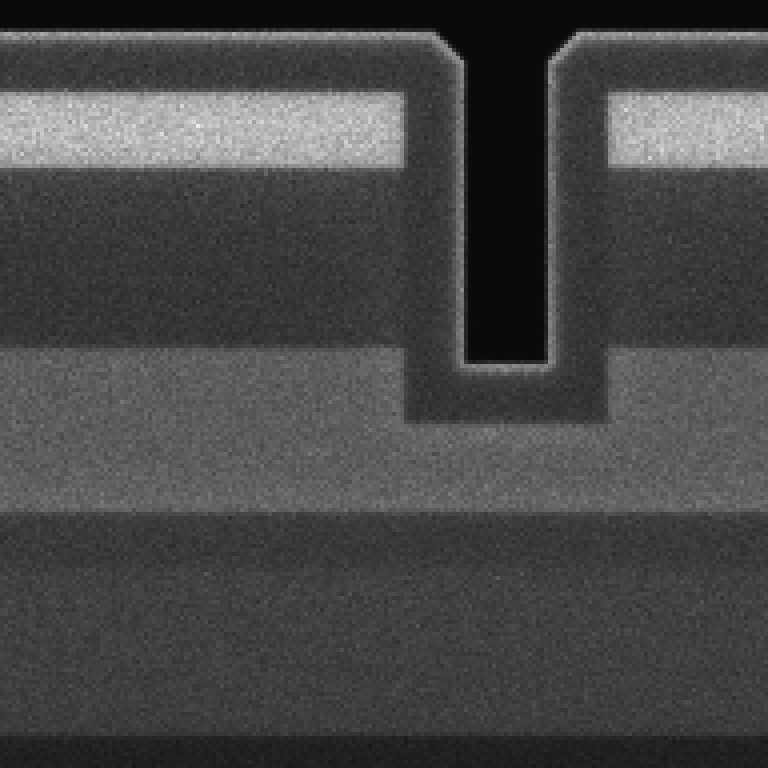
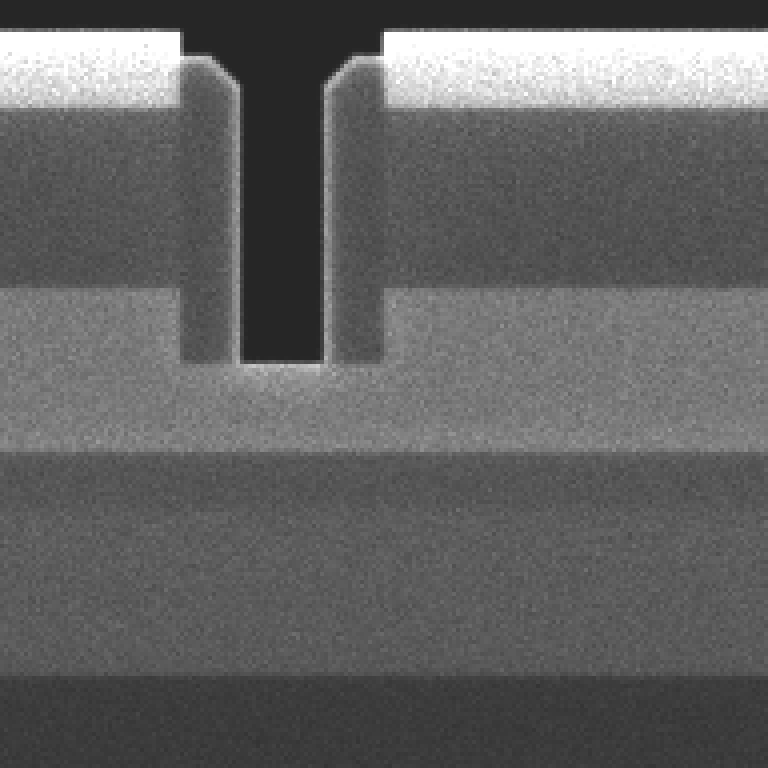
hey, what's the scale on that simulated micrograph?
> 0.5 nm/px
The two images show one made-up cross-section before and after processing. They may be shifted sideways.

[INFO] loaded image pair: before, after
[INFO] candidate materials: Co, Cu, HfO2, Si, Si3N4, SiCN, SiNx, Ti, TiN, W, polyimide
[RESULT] removed SiNx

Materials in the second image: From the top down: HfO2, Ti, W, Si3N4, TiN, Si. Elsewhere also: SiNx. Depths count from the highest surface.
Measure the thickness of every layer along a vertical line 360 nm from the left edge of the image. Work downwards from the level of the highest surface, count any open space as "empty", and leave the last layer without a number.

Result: HfO2 38, Ti 90, W 82, Si3N4 28, TiN 84, Si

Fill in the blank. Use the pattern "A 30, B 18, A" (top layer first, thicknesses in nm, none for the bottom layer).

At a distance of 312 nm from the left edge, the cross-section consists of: HfO2 38, Ti 90, W 82, Si3N4 28, TiN 84, Si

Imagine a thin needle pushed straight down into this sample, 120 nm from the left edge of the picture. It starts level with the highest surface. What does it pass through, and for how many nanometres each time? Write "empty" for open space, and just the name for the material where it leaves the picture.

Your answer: empty 166, W 44, Si3N4 28, TiN 84, Si